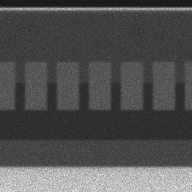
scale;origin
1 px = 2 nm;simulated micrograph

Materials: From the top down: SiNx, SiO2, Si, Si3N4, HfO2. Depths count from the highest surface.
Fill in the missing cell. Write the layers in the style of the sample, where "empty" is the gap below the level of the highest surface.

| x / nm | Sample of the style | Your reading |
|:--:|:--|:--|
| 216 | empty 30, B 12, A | SiNx 108, SiO2 96, Si 60, Si3N4 54, HfO2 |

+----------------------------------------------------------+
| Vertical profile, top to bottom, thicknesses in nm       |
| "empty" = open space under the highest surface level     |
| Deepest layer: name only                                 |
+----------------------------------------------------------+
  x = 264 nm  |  SiNx 108, SiO2 96, Si 60, Si3N4 54, HfO2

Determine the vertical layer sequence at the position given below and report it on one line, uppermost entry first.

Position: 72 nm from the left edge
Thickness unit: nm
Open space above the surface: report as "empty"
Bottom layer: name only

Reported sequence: SiNx 108, SiO2 96, Si 60, Si3N4 54, HfO2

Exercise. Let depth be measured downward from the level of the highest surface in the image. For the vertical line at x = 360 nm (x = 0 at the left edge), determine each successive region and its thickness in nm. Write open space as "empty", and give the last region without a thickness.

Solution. SiNx 150, Si 114, Si3N4 54, HfO2